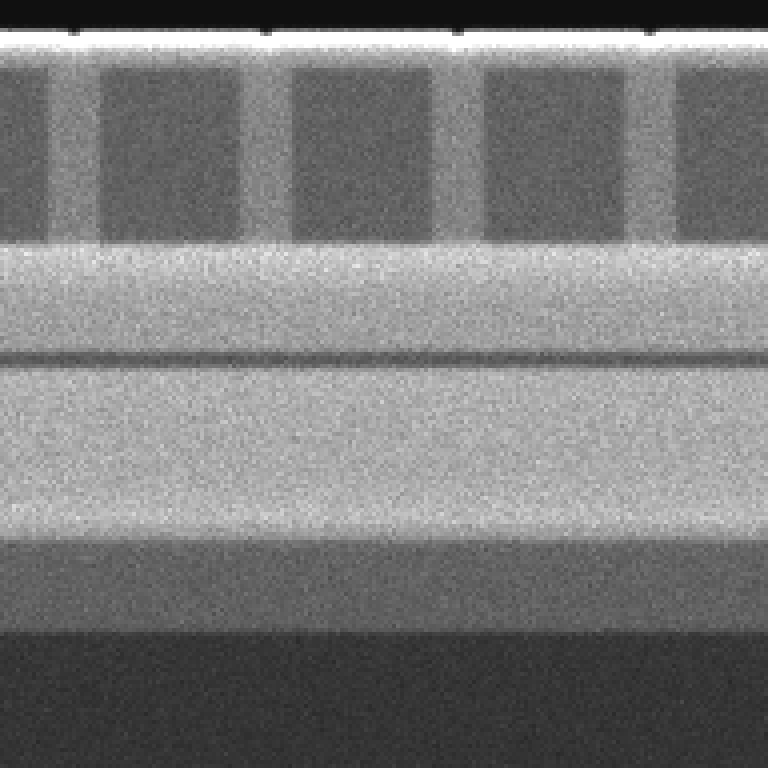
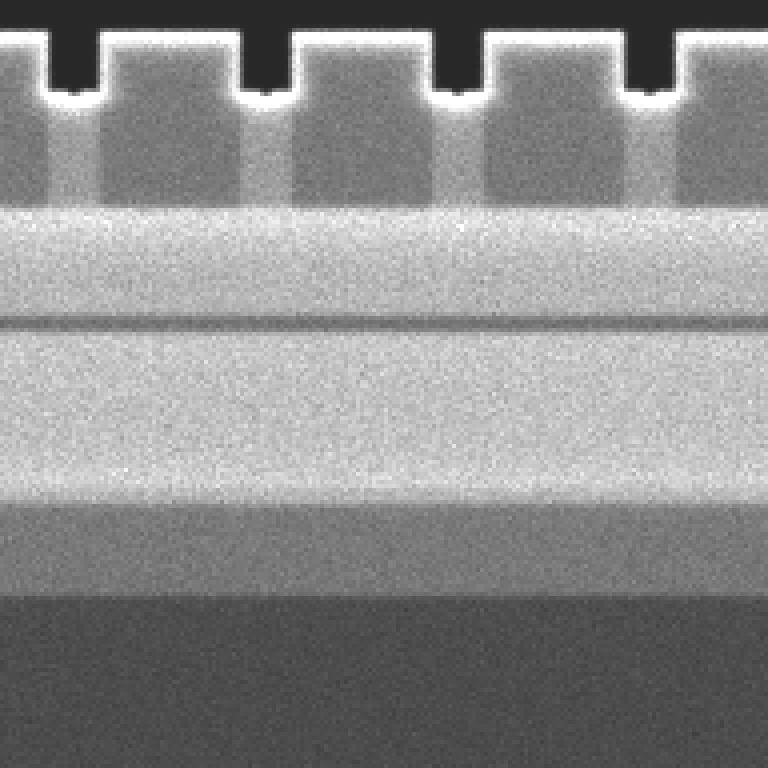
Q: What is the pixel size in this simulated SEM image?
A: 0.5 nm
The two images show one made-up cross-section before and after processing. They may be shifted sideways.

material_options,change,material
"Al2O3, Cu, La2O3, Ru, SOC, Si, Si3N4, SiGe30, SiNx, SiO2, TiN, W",removed,SiO2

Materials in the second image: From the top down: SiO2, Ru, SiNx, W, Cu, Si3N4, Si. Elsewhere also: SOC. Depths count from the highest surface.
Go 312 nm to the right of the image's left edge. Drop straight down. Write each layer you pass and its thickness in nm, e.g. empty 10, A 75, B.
empty 30, SiO2 58, Ru 54, SiNx 8, W 78, Cu 8, Si3N4 46, Si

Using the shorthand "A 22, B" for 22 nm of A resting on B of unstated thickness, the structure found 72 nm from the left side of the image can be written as SOC 88, Ru 54, SiNx 8, W 78, Cu 8, Si3N4 46, Si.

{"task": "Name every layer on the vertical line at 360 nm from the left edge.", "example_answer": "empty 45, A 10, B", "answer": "SOC 88, Ru 54, SiNx 8, W 78, Cu 8, Si3N4 46, Si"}